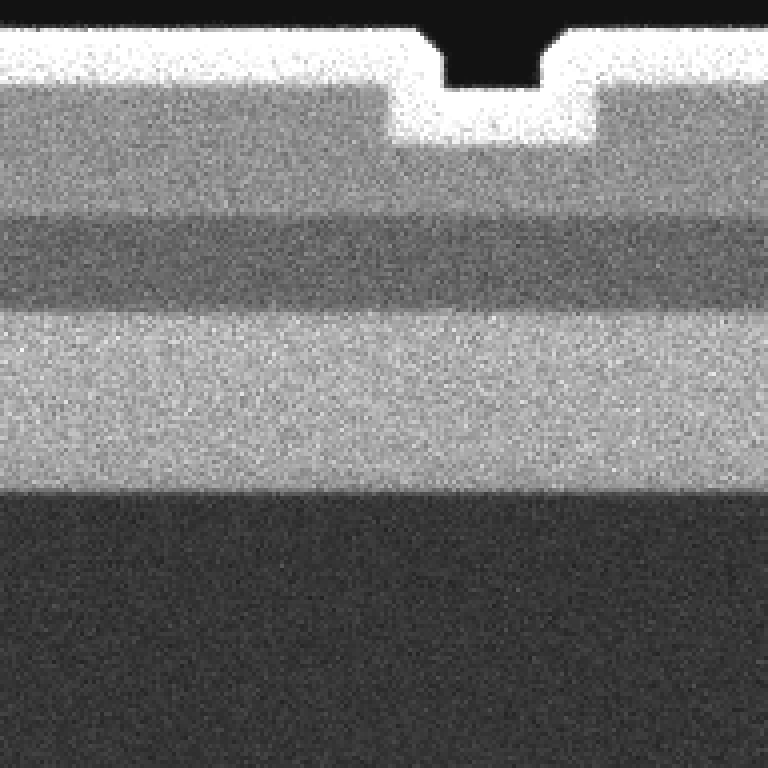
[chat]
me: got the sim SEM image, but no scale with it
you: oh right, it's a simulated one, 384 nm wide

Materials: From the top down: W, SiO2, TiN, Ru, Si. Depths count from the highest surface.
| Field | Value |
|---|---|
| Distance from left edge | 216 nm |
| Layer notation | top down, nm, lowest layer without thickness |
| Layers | empty 10, W 46, SiO2 36, TiN 48, Ru 90, Si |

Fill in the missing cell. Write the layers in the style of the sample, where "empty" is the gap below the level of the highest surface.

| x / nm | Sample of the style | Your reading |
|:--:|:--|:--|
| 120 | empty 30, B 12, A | W 26, SiO2 66, TiN 48, Ru 90, Si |